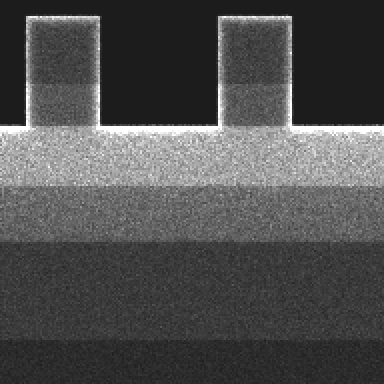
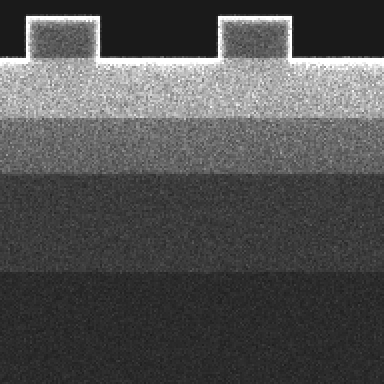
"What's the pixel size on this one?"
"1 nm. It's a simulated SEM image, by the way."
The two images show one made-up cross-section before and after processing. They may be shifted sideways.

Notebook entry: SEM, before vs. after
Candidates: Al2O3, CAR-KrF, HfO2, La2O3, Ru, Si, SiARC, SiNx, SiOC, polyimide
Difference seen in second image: SiARC removed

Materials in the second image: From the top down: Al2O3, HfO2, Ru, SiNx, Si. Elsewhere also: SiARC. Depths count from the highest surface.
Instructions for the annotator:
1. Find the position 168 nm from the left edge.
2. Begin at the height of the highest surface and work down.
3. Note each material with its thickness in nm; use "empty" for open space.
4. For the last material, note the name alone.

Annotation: empty 42, HfO2 60, Ru 56, SiNx 98, Si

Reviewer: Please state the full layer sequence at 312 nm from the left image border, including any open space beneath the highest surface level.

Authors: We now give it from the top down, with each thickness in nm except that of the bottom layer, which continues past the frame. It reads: empty 42, HfO2 60, Ru 56, SiNx 98, Si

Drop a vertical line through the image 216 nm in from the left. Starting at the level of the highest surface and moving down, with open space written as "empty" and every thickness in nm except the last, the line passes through empty 42, HfO2 60, Ru 56, SiNx 98, Si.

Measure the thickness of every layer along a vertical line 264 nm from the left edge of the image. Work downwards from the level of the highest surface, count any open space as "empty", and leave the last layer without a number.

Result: Al2O3 42, HfO2 60, Ru 56, SiNx 98, Si